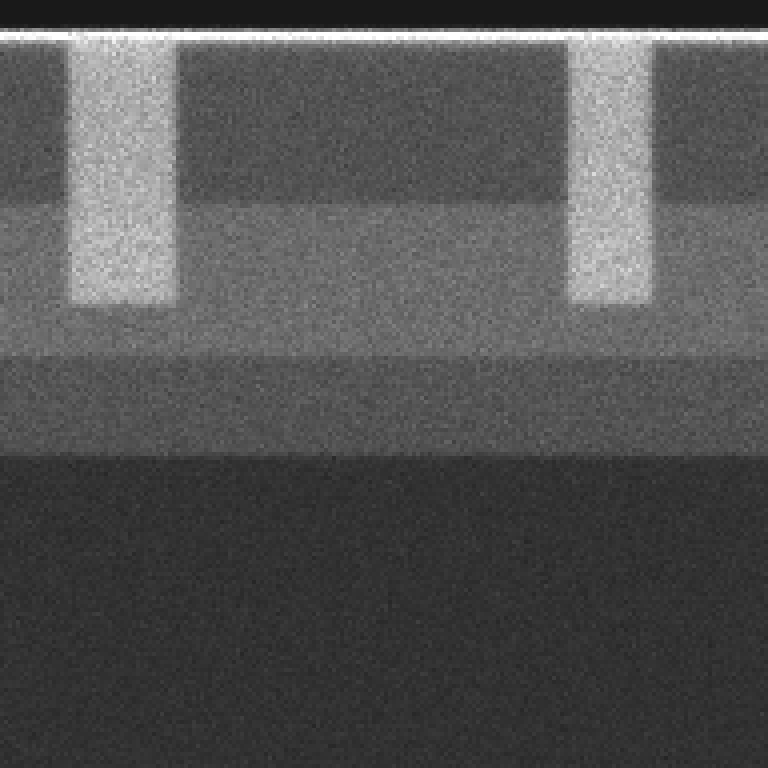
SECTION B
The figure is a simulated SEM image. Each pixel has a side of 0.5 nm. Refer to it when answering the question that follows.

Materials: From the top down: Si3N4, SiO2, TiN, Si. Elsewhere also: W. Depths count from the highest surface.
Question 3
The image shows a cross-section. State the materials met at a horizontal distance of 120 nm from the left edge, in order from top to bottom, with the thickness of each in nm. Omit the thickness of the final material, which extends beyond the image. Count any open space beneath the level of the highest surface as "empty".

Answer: Si3N4 86, SiO2 76, TiN 50, Si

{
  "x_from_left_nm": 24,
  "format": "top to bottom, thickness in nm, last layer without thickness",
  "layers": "Si3N4 86, SiO2 76, TiN 50, Si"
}